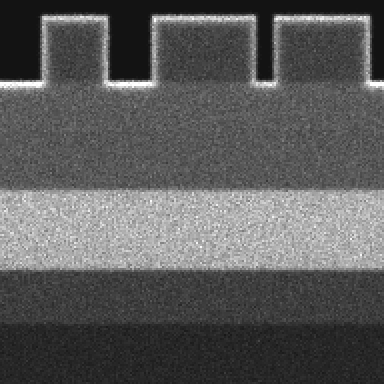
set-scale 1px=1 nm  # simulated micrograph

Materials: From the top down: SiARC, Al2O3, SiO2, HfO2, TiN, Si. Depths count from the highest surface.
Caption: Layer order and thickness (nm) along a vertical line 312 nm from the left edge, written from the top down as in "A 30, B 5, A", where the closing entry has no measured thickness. SiARC 66, Al2O3 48, SiO2 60, HfO2 80, TiN 54, Si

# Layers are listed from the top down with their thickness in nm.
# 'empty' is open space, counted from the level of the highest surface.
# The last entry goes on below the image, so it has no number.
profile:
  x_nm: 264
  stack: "empty 66, Al2O3 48, SiO2 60, HfO2 80, TiN 54, Si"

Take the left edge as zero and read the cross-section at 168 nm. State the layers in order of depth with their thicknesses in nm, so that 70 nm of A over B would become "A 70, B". SiARC 66, Al2O3 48, SiO2 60, HfO2 80, TiN 54, Si